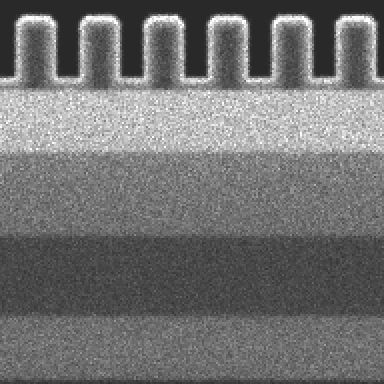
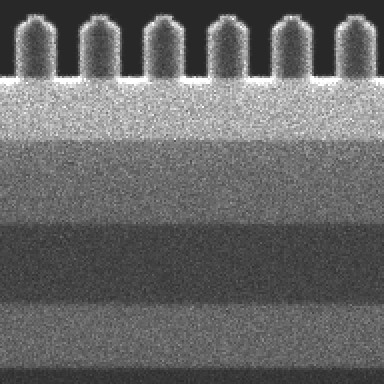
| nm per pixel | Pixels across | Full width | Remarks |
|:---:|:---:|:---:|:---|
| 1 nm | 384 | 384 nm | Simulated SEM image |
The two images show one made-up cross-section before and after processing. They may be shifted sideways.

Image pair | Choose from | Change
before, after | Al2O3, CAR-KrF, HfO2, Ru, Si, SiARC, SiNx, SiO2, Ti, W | SiO2 (removed)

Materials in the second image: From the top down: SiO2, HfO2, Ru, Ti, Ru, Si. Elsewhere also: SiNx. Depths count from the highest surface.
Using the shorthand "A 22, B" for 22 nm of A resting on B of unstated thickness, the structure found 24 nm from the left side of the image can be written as empty 6, SiO2 56, HfO2 62, Ru 84, Ti 80, Ru 64, Si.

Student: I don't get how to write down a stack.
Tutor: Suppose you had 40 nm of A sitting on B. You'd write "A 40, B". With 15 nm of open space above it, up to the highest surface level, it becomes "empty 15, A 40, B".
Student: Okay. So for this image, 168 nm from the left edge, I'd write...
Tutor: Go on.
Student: SiNx 62, HfO2 62, Ru 84, Ti 80, Ru 64, Si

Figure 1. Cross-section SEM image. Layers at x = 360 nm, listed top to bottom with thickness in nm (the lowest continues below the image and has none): SiNx 62, HfO2 62, Ru 84, Ti 80, Ru 64, Si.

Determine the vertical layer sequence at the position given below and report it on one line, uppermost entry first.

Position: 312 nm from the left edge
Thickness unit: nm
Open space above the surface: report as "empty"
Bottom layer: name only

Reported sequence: empty 62, HfO2 62, Ru 84, Ti 80, Ru 64, Si